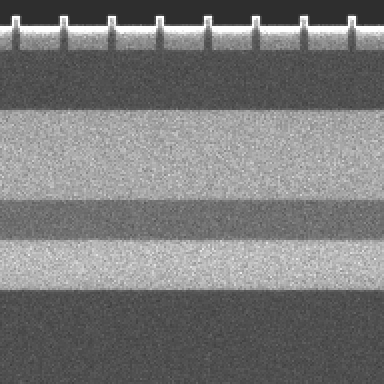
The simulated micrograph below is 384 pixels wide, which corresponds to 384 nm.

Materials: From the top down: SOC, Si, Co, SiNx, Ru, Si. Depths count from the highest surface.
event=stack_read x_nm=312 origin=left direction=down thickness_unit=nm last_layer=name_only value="empty 10, SOC 24, Si 60, Co 90, SiNx 40, Ru 50, Si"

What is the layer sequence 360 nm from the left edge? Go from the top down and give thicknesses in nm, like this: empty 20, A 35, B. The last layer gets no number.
empty 10, SOC 24, Si 60, Co 90, SiNx 40, Ru 50, Si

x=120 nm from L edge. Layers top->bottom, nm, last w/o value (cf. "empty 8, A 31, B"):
empty 10, SOC 24, Si 60, Co 90, SiNx 40, Ru 50, Si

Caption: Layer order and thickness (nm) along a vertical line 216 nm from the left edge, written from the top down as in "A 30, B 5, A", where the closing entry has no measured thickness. empty 10, SOC 24, Si 60, Co 90, SiNx 40, Ru 50, Si